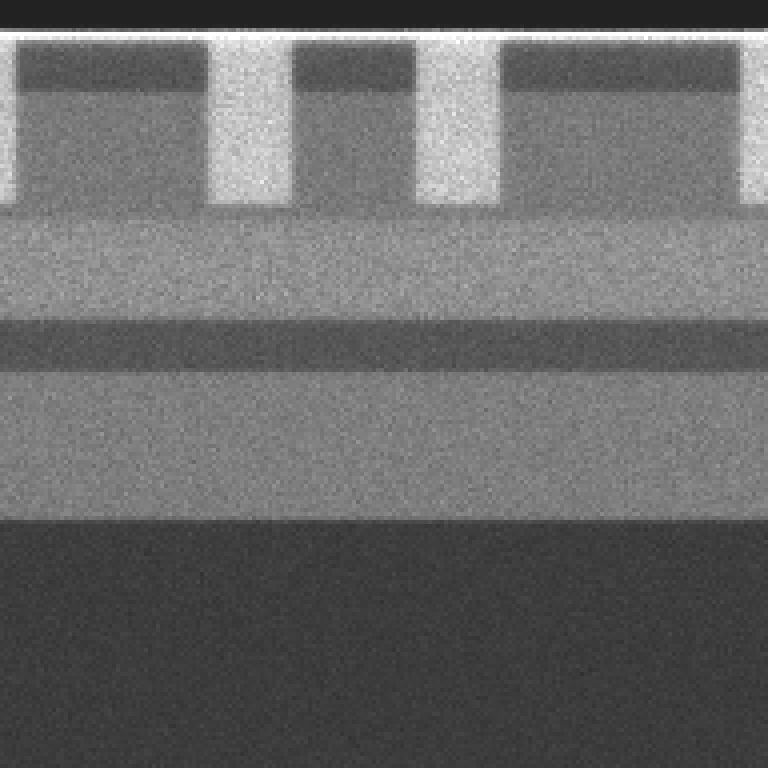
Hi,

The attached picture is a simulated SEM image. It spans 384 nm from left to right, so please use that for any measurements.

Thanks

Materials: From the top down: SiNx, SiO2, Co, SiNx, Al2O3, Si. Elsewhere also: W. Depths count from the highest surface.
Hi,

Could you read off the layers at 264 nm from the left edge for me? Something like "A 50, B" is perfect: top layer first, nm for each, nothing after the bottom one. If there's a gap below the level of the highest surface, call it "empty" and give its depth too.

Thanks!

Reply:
SiNx 30, SiO2 64, Co 50, SiNx 26, Al2O3 74, Si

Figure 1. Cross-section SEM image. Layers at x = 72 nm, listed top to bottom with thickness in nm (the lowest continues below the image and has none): SiNx 30, SiO2 64, Co 50, SiNx 26, Al2O3 74, Si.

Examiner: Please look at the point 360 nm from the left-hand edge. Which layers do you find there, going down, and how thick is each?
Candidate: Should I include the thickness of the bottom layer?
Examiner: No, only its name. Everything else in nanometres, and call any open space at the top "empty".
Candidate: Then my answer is SiNx 30, SiO2 64, Co 50, SiNx 26, Al2O3 74, Si